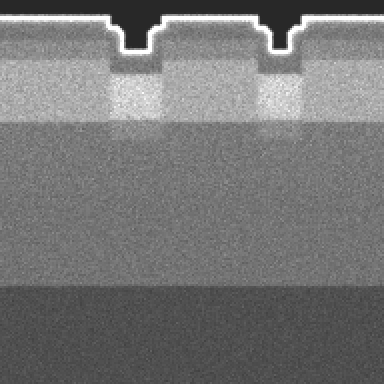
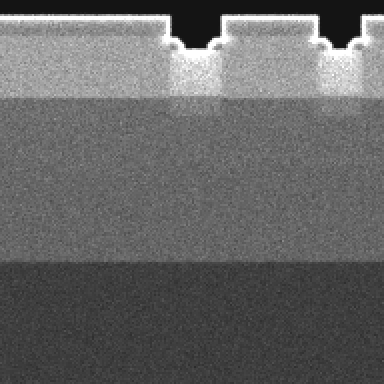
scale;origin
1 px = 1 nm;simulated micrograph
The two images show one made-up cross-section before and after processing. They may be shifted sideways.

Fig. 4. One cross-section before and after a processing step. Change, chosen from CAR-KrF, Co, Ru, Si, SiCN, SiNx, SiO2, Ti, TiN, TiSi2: SiNx removed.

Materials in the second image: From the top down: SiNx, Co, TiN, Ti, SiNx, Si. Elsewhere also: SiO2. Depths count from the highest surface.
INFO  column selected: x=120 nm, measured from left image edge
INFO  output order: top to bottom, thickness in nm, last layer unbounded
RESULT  TiN 20, SiO2 62, Ti 76, SiNx 88, Si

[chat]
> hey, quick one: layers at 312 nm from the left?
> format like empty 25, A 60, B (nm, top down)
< TiN 20, SiO2 62, Ti 76, SiNx 88, Si